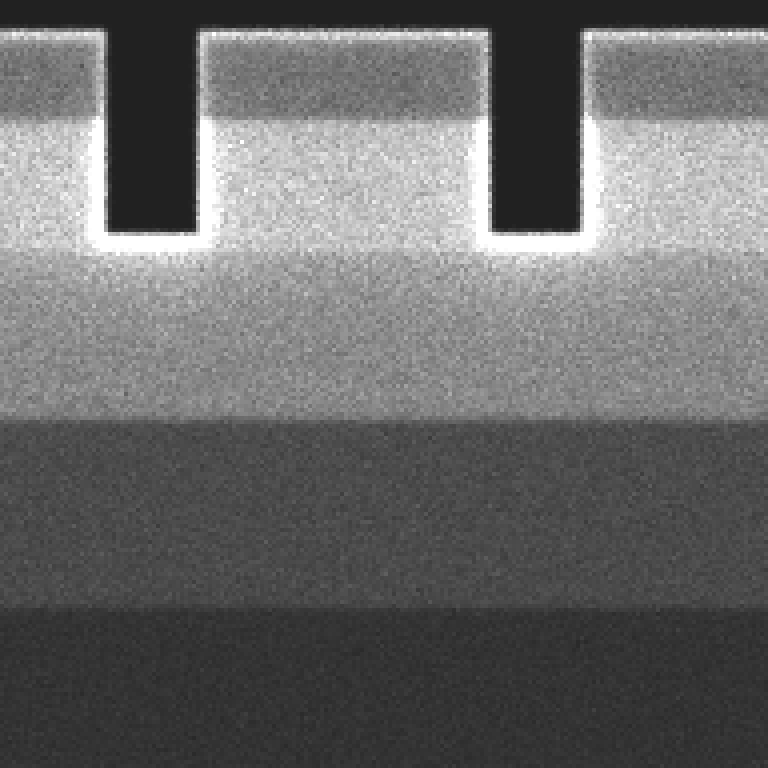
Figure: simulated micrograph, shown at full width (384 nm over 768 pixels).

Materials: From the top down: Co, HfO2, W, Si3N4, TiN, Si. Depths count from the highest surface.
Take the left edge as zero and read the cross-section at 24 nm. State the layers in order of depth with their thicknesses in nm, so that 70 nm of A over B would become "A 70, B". Co 44, HfO2 66, W 84, Si3N4 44, TiN 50, Si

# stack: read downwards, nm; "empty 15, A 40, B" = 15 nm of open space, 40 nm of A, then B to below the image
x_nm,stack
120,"Co 44, HfO2 66, W 84, Si3N4 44, TiN 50, Si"